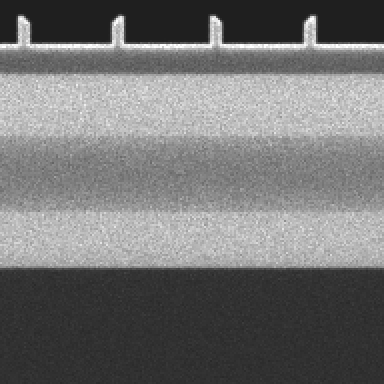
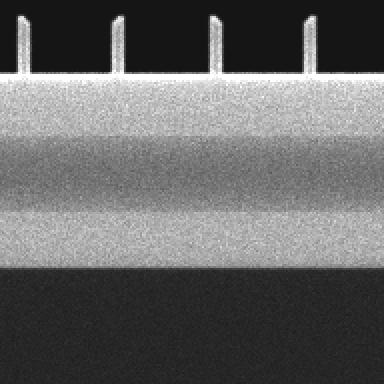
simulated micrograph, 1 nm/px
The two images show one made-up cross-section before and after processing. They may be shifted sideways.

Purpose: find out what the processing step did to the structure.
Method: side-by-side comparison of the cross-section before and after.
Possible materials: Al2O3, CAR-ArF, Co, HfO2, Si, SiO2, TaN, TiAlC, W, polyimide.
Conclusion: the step removed Al2O3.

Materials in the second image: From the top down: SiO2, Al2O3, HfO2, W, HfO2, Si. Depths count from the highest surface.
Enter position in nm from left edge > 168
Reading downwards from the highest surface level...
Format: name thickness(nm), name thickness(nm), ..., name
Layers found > empty 58, HfO2 62, W 76, HfO2 56, Si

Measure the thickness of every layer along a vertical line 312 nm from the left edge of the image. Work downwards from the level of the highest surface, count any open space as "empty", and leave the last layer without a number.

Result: SiO2 28, Al2O3 30, HfO2 62, W 76, HfO2 56, Si